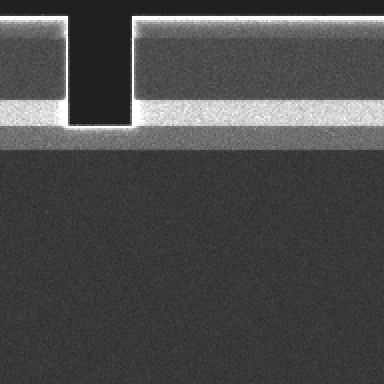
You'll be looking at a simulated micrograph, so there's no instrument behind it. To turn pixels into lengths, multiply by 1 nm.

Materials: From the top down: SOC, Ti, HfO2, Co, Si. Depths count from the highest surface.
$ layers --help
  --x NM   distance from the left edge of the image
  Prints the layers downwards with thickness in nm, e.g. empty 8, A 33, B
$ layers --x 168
SOC 22, Ti 62, HfO2 26, Co 24, Si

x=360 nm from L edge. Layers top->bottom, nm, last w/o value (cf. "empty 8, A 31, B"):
SOC 22, Ti 62, HfO2 26, Co 24, Si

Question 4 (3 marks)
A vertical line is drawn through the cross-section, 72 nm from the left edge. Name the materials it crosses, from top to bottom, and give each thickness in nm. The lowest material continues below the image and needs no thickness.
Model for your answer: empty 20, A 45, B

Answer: empty 110, Co 24, Si